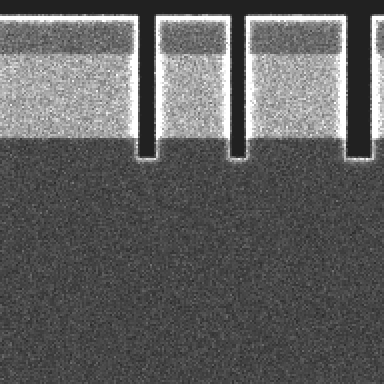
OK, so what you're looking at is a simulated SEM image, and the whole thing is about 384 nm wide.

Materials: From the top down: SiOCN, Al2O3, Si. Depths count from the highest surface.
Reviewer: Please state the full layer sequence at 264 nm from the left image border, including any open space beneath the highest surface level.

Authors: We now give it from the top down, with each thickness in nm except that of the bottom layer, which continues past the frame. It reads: SiOCN 38, Al2O3 84, Si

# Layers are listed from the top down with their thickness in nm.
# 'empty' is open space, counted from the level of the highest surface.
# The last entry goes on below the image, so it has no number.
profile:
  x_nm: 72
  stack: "SiOCN 38, Al2O3 84, Si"